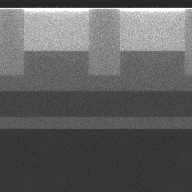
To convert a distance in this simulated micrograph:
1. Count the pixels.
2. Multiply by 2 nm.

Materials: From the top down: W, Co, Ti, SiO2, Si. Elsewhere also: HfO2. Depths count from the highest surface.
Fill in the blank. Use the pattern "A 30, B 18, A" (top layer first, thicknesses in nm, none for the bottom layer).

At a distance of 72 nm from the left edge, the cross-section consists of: HfO2 86, Co 80, Ti 52, SiO2 24, Si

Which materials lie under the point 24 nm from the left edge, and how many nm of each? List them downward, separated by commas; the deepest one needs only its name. W 134, Co 32, Ti 52, SiO2 24, Si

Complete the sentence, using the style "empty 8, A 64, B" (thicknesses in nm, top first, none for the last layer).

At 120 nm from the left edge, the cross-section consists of HfO2 86, Co 80, Ti 52, SiO2 24, Si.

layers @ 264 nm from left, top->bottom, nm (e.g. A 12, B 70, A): HfO2 86, Co 80, Ti 52, SiO2 24, Si